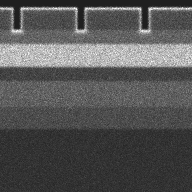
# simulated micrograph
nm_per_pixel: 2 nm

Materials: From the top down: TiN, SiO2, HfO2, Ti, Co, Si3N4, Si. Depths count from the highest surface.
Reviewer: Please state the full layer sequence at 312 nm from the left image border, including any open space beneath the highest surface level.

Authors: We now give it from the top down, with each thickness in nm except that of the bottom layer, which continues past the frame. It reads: TiN 44, SiO2 28, HfO2 46, Ti 28, Co 52, Si3N4 44, Si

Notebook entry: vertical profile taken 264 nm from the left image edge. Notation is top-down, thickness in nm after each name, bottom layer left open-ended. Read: TiN 44, SiO2 28, HfO2 46, Ti 28, Co 52, Si3N4 44, Si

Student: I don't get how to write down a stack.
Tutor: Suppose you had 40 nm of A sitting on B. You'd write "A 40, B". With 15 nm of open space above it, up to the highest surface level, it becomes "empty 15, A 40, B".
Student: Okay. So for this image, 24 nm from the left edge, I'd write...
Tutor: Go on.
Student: TiN 44, SiO2 28, HfO2 46, Ti 28, Co 52, Si3N4 44, Si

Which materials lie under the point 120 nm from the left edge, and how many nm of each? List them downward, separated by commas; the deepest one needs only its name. TiN 44, SiO2 28, HfO2 46, Ti 28, Co 52, Si3N4 44, Si